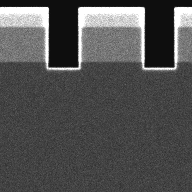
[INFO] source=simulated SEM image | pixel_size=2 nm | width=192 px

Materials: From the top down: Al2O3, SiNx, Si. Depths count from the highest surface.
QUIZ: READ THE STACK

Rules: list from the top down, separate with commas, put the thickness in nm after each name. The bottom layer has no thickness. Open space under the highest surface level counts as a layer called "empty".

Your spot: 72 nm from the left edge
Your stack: Al2O3 38, SiNx 70, Si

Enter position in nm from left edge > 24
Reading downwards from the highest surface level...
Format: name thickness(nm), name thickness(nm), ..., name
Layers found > Al2O3 38, SiNx 70, Si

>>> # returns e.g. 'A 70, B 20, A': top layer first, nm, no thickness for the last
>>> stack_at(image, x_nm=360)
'Al2O3 38, SiNx 70, Si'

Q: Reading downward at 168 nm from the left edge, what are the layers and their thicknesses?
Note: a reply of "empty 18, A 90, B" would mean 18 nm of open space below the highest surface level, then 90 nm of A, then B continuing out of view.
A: Al2O3 38, SiNx 70, Si